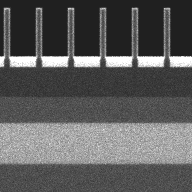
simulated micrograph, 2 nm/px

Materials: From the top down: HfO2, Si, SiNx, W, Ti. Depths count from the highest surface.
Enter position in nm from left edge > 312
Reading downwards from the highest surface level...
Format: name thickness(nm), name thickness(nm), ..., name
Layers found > empty 98, HfO2 20, Si 60, SiNx 52, W 82, Ti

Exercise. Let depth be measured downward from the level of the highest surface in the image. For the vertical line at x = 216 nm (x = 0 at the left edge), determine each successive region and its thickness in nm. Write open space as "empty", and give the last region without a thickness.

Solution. empty 98, HfO2 20, Si 60, SiNx 52, W 82, Ti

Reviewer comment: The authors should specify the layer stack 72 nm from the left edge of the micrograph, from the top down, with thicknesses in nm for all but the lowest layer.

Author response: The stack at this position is Si 178, SiNx 52, W 82, Ti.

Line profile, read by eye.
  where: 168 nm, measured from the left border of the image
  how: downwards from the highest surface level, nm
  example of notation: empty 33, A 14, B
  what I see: empty 98, HfO2 20, Si 60, SiNx 52, W 82, Ti